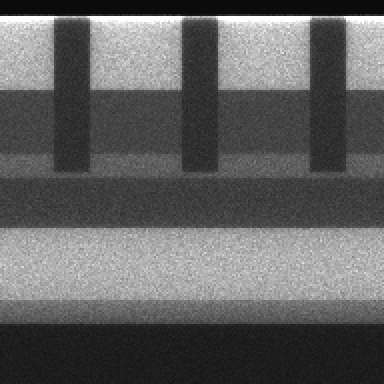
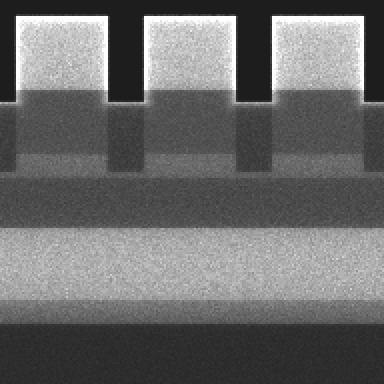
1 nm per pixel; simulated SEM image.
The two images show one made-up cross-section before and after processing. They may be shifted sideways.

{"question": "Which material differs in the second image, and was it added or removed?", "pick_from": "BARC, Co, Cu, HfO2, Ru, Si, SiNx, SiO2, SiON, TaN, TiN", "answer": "SiNx, removed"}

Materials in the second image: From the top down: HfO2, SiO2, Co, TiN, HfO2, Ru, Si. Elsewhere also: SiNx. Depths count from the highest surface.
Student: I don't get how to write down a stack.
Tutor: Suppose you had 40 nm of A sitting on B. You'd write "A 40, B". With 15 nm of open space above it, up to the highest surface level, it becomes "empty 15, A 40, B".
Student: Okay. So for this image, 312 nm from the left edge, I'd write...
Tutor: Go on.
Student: HfO2 74, SiO2 64, Co 24, TiN 50, HfO2 72, Ru 24, Si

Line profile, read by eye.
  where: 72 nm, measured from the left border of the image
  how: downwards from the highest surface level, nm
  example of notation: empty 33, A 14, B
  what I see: HfO2 74, SiO2 64, Co 24, TiN 50, HfO2 72, Ru 24, Si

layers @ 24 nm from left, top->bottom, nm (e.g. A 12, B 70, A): HfO2 74, SiO2 64, Co 24, TiN 50, HfO2 72, Ru 24, Si